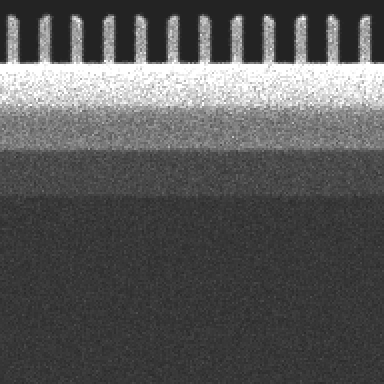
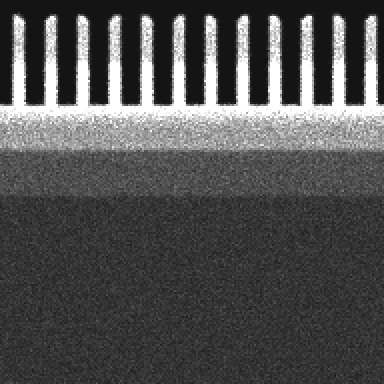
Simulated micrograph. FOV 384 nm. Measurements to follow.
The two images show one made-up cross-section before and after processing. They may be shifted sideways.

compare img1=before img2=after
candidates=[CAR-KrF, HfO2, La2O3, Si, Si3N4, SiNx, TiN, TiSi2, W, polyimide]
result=removed:HfO2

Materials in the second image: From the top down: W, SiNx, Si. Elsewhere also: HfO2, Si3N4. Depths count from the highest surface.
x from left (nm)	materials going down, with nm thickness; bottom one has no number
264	empty 90, W 44, SiNx 46, Si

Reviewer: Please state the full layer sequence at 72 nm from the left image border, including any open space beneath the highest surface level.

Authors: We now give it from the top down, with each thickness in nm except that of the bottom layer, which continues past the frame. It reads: empty 90, W 44, SiNx 46, Si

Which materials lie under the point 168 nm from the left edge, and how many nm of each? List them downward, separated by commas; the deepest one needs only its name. empty 90, W 44, SiNx 46, Si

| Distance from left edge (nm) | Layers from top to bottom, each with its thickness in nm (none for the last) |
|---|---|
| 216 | empty 90, W 44, SiNx 46, Si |